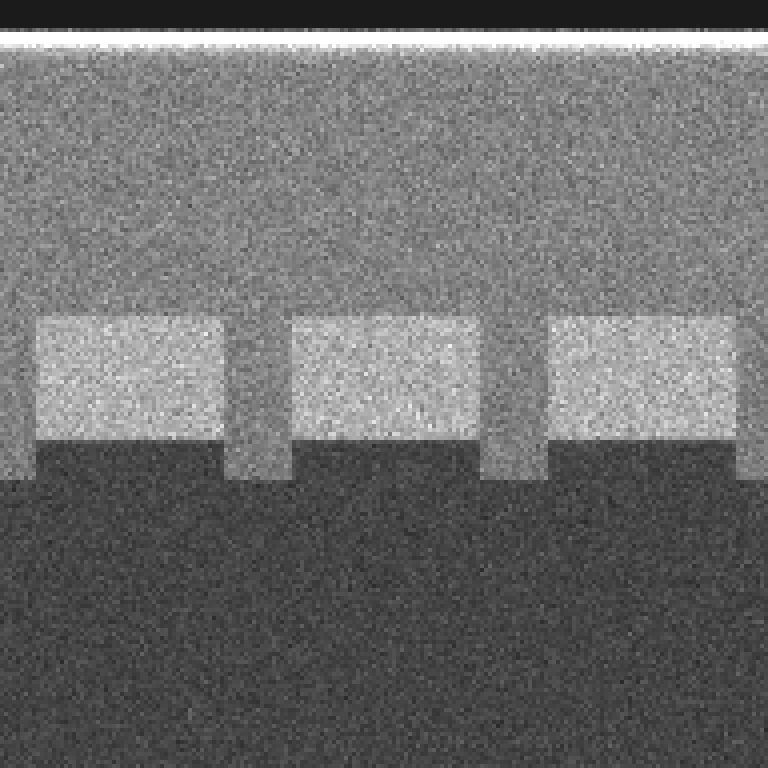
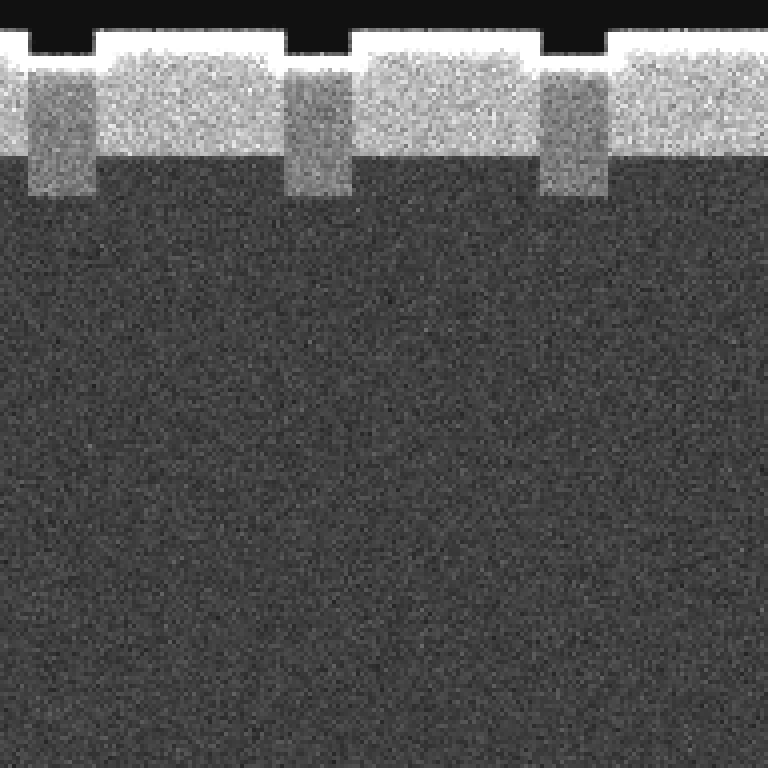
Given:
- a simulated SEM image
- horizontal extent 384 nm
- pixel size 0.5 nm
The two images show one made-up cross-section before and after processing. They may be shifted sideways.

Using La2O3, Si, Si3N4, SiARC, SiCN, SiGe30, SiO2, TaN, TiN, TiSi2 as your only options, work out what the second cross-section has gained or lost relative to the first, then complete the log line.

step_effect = removed SiARC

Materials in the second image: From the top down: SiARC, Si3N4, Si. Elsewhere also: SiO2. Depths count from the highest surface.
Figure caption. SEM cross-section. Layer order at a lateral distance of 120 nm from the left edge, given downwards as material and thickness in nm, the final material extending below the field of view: SiO2 62, Si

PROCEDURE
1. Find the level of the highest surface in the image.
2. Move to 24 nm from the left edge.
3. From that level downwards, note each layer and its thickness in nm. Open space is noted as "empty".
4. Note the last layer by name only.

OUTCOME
empty 12, SiARC 24, Si3N4 46, Si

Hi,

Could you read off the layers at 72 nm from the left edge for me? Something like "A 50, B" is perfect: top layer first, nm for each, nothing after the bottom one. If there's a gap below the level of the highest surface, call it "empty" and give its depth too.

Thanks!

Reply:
SiO2 62, Si